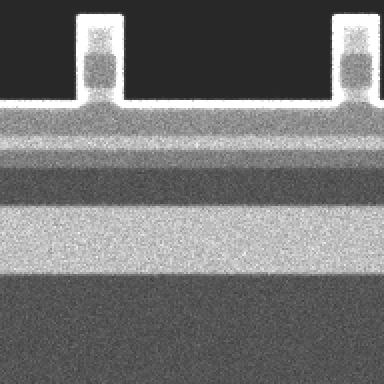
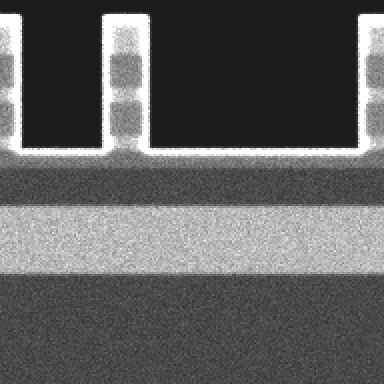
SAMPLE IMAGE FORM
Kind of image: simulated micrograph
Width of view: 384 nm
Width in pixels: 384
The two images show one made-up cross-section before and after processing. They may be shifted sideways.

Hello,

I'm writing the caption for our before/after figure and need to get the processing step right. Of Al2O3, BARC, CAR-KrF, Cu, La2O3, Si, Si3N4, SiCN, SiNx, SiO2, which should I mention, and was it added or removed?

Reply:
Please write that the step removed Si3N4 and SiO2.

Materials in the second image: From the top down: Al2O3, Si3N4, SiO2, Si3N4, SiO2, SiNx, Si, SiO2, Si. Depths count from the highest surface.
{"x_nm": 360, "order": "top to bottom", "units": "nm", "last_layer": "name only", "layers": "Al2O3 38, Si3N4 34, SiO2 14, Si3N4 34, SiO2 14, SiNx 18, Si 38, SiO2 68, Si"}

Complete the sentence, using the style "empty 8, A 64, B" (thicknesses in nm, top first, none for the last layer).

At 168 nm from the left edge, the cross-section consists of empty 134, SiNx 18, Si 38, SiO2 68, Si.